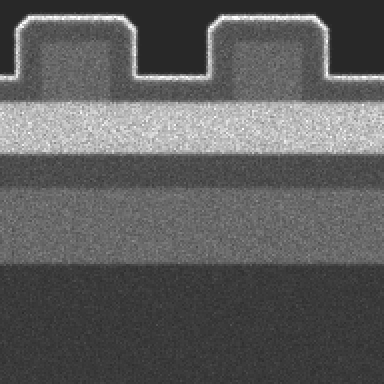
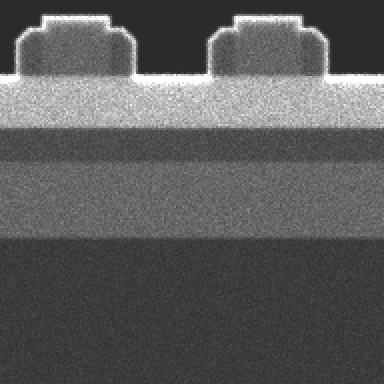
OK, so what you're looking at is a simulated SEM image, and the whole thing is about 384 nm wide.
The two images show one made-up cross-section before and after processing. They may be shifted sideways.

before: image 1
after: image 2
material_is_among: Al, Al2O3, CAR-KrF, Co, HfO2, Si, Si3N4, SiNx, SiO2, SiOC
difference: Si3N4, removed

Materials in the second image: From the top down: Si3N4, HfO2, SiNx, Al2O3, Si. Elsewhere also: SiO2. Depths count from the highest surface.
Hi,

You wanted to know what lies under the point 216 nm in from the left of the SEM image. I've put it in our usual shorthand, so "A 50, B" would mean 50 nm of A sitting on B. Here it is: empty 16, Si3N4 44, HfO2 52, SiNx 34, Al2O3 76, Si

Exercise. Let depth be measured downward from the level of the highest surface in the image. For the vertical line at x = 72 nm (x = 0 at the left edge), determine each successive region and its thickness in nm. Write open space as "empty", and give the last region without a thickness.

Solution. SiO2 60, HfO2 52, SiNx 34, Al2O3 76, Si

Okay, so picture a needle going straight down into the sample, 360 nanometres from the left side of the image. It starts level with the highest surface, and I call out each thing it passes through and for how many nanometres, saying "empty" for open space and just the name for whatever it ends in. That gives empty 60, HfO2 52, SiNx 34, Al2O3 76, Si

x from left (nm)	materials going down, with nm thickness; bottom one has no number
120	empty 12, Si3N4 48, HfO2 52, SiNx 34, Al2O3 76, Si